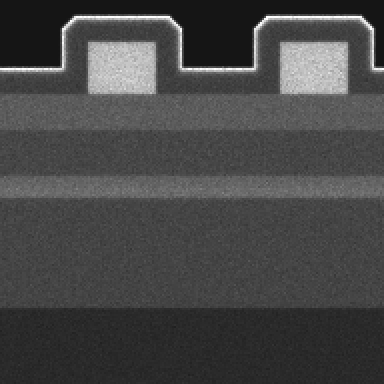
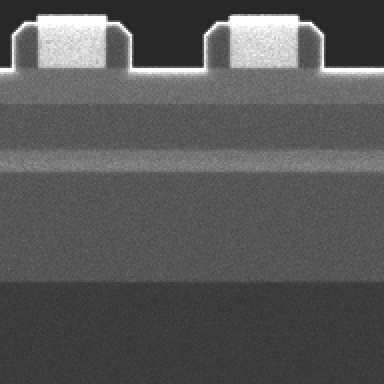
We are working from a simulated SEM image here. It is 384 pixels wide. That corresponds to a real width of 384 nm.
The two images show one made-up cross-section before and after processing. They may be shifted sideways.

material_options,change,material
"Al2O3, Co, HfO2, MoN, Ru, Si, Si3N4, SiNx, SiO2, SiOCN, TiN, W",removed,SiNx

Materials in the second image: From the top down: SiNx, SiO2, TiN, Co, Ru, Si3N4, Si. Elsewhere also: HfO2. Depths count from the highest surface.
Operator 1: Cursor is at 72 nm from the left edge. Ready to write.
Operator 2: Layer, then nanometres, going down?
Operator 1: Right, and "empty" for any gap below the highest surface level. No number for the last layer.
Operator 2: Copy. HfO2 52, SiO2 36, TiN 46, Co 12, Ru 10, Si3N4 110, Si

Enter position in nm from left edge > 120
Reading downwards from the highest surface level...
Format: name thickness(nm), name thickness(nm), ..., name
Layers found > empty 8, SiNx 44, SiO2 36, TiN 46, Co 12, Ru 10, Si3N4 110, Si